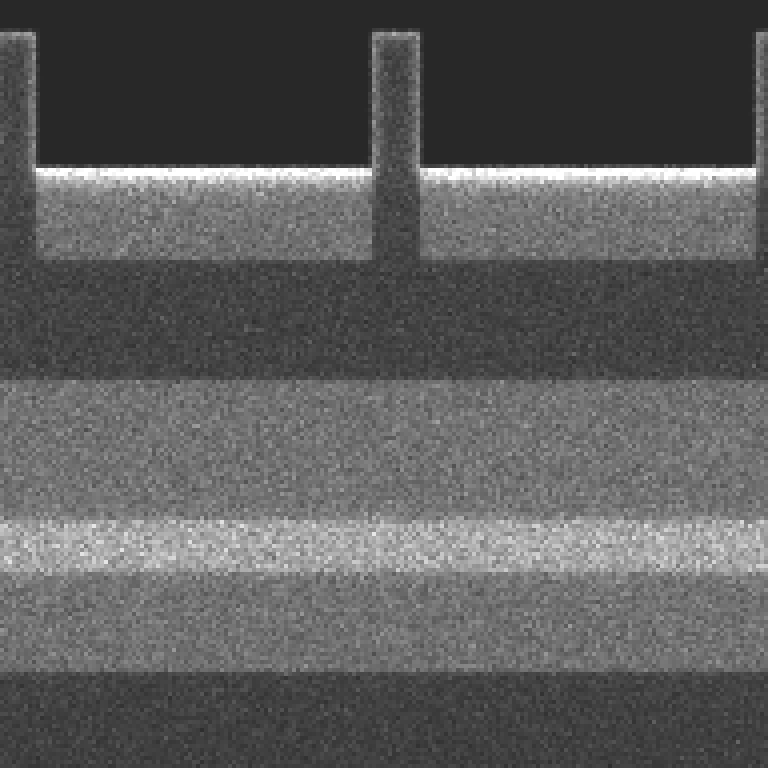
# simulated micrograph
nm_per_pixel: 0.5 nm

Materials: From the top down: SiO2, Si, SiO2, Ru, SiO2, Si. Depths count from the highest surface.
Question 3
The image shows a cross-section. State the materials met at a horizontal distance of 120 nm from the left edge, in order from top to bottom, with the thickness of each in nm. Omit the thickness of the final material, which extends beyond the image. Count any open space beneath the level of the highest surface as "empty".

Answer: empty 68, SiO2 46, Si 60, SiO2 70, Ru 26, SiO2 50, Si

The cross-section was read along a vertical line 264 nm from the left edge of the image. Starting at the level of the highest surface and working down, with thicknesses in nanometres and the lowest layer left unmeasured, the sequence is empty 68, SiO2 46, Si 60, SiO2 70, Ru 26, SiO2 50, Si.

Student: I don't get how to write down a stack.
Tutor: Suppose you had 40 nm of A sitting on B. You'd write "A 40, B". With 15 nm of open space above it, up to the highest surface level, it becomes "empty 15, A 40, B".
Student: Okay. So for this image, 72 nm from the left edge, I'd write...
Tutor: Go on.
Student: empty 68, SiO2 46, Si 60, SiO2 70, Ru 26, SiO2 50, Si